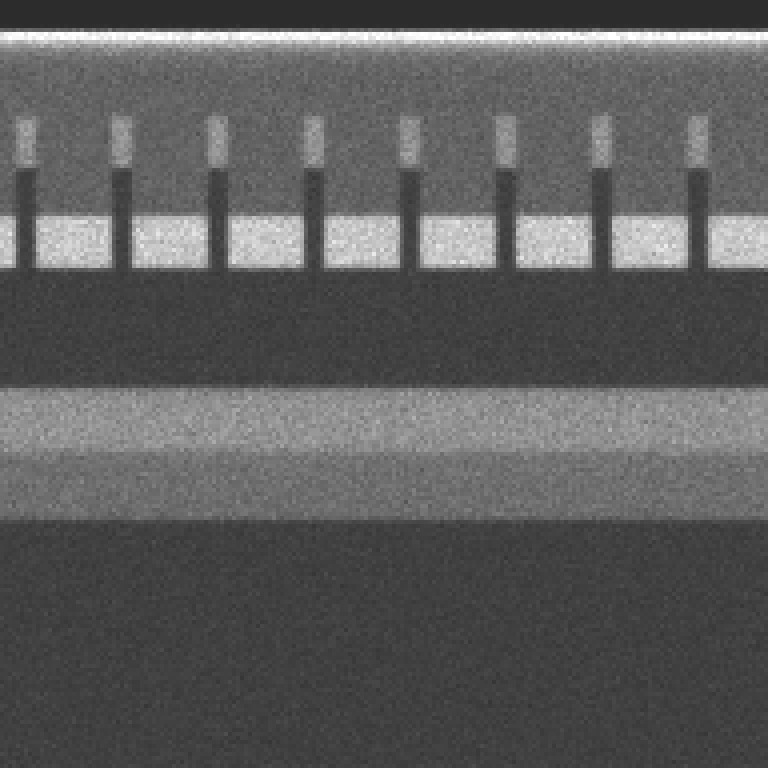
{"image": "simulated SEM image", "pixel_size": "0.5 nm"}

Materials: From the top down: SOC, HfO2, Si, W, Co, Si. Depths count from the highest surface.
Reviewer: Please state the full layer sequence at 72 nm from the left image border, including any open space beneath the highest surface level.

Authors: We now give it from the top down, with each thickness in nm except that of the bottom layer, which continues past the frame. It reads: SOC 92, HfO2 26, Si 60, W 32, Co 34, Si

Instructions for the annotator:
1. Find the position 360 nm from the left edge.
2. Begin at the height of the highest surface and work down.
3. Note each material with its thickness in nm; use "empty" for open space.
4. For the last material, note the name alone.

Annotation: SOC 92, HfO2 26, Si 60, W 32, Co 34, Si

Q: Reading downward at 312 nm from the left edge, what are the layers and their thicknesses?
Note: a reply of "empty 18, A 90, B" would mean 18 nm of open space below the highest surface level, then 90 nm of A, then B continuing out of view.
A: SOC 92, HfO2 26, Si 60, W 32, Co 34, Si